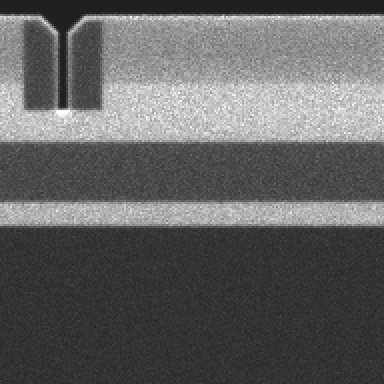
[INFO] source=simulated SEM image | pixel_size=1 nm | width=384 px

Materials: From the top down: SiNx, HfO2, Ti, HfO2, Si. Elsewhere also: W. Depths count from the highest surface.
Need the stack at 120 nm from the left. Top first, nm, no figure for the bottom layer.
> W 68, HfO2 58, Ti 60, HfO2 24, Si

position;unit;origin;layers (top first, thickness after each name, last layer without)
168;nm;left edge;W 68, HfO2 58, Ti 60, HfO2 24, Si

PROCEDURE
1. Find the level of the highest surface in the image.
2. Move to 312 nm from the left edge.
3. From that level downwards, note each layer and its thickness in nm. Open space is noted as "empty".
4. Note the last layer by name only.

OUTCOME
W 68, HfO2 58, Ti 60, HfO2 24, Si